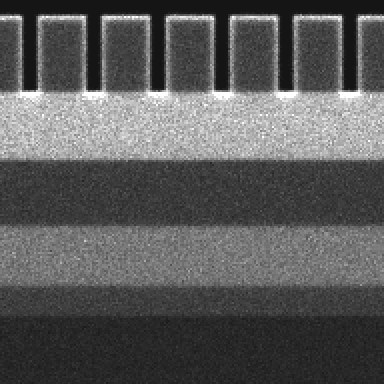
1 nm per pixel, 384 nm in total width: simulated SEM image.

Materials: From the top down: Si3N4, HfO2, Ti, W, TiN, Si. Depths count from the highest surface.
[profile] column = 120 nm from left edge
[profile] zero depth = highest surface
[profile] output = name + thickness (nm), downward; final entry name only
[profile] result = Si3N4 76, HfO2 68, Ti 66, W 60, TiN 30, Si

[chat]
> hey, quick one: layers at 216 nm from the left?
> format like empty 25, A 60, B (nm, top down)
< empty 76, HfO2 68, Ti 66, W 60, TiN 30, Si